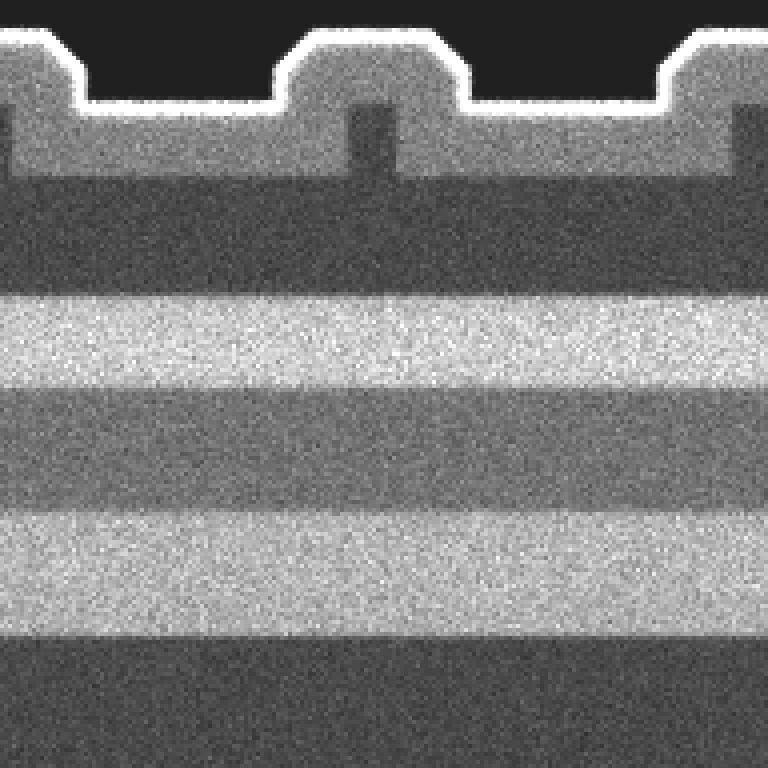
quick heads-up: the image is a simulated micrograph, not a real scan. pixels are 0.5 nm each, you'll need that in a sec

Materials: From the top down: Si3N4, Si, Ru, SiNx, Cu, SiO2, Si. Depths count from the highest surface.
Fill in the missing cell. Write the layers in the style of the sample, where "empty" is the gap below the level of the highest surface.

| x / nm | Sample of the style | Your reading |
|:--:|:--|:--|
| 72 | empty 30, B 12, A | empty 36, Si3N4 36, Si 60, Ru 46, SiNx 62, Cu 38, SiO2 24, Si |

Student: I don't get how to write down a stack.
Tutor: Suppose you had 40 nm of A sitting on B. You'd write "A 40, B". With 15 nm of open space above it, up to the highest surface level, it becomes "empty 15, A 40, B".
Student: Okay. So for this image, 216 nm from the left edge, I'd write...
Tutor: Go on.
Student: empty 2, Si3N4 70, Si 60, Ru 46, SiNx 62, Cu 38, SiO2 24, Si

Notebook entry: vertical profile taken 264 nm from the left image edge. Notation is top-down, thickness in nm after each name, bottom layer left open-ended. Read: empty 36, Si3N4 36, Si 60, Ru 46, SiNx 62, Cu 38, SiO2 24, Si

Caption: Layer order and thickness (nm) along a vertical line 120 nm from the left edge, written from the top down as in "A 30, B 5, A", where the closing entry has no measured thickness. empty 36, Si3N4 36, Si 60, Ru 46, SiNx 62, Cu 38, SiO2 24, Si